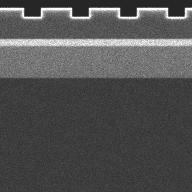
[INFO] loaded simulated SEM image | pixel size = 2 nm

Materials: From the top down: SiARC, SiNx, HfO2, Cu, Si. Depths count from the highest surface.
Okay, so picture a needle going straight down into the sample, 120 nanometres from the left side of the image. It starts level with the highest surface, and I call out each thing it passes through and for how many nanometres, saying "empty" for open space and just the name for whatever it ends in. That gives SiARC 18, SiNx 44, HfO2 14, Cu 64, Si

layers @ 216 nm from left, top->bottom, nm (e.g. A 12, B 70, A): SiARC 18, SiNx 44, HfO2 14, Cu 64, Si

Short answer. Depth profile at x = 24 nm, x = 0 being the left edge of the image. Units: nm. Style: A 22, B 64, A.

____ SiARC 18, SiNx 44, HfO2 14, Cu 64, Si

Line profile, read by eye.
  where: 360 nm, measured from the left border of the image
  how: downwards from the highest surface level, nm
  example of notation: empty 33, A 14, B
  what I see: empty 18, SiNx 44, HfO2 14, Cu 64, Si